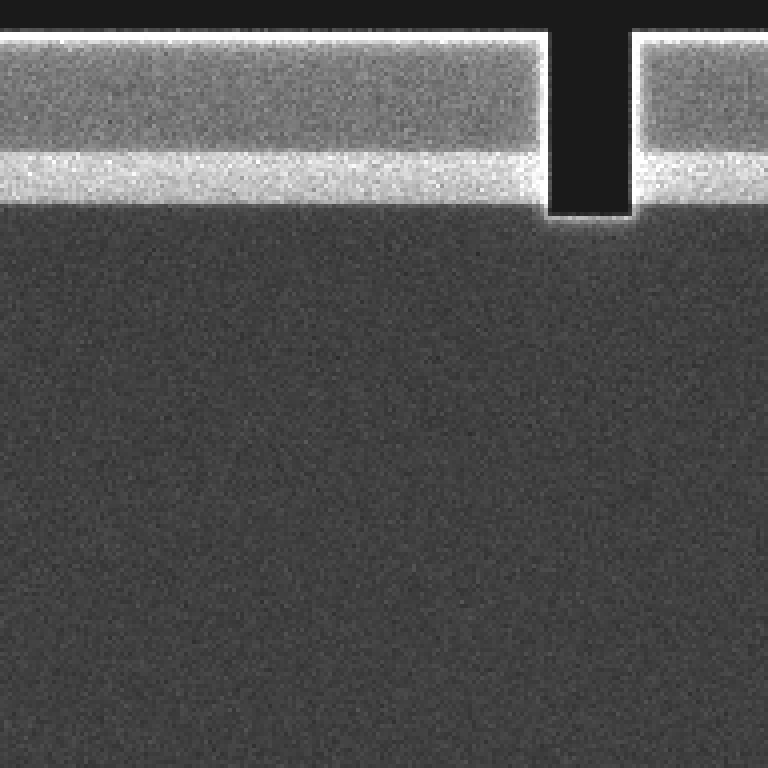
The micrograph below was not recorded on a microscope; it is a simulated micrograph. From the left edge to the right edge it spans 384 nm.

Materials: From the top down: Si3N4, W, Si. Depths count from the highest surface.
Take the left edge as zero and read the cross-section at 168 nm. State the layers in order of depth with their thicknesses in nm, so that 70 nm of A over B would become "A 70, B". Si3N4 60, W 26, Si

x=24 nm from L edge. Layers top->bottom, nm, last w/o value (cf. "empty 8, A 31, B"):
Si3N4 60, W 26, Si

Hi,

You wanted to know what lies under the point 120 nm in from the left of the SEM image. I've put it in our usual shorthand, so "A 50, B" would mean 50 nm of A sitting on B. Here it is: Si3N4 60, W 26, Si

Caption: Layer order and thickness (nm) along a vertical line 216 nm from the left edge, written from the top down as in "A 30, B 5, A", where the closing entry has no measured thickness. Si3N4 60, W 26, Si